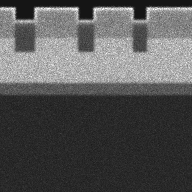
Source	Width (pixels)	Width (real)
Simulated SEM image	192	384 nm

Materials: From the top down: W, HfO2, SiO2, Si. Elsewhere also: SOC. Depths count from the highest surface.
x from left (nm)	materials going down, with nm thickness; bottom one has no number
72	W 60, HfO2 90, SiO2 24, Si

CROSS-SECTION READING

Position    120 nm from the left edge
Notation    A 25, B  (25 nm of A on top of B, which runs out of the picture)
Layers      W 60, HfO2 90, SiO2 24, Si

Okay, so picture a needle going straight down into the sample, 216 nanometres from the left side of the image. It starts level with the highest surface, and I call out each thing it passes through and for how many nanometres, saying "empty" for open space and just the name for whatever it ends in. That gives W 60, HfO2 90, SiO2 24, Si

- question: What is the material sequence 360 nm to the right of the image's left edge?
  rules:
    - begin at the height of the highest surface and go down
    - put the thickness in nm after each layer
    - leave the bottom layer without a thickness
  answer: W 60, HfO2 90, SiO2 24, Si